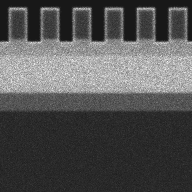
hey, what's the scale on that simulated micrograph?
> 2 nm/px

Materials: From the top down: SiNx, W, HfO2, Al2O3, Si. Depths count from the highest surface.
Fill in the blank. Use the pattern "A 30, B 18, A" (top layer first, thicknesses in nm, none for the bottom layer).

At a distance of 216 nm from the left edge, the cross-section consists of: SiNx 62, W 34, HfO2 74, Al2O3 36, Si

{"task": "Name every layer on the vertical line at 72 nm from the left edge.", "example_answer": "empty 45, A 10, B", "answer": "empty 68, W 28, HfO2 74, Al2O3 36, Si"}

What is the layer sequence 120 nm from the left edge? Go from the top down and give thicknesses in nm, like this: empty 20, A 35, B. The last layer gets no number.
empty 68, W 28, HfO2 74, Al2O3 36, Si